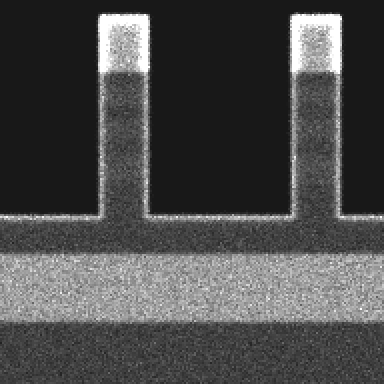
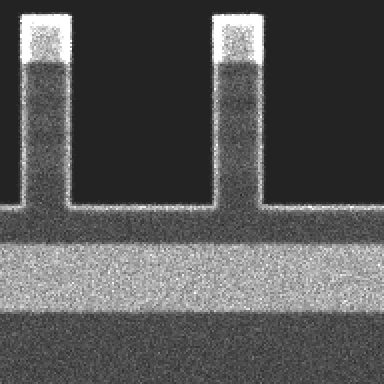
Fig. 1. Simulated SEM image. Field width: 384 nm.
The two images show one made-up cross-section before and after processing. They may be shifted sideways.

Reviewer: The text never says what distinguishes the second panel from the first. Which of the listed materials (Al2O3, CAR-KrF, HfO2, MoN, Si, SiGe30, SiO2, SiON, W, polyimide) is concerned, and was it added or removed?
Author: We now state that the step removed Al2O3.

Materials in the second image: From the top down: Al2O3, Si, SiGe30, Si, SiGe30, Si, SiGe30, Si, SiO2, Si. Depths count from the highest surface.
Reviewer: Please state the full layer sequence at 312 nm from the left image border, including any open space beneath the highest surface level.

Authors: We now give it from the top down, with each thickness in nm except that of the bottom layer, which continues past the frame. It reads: empty 190, Si 38, SiO2 68, Si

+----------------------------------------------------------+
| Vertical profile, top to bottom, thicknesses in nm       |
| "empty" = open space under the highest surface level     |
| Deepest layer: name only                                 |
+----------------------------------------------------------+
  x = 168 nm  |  empty 190, Si 38, SiO2 68, Si